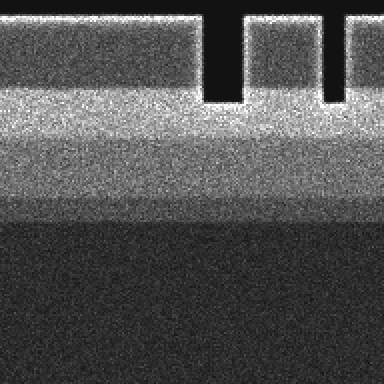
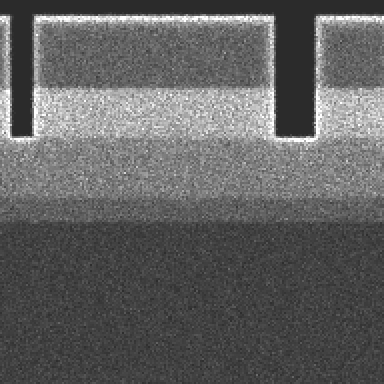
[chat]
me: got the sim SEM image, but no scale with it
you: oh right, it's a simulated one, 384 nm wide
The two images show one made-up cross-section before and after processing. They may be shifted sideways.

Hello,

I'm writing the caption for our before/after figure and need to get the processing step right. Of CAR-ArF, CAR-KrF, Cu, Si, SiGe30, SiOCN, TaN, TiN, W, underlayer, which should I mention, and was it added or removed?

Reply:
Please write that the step removed W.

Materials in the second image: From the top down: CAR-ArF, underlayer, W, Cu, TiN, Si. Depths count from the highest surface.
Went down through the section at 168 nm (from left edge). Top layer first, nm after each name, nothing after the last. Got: CAR-ArF 40, underlayer 32, W 50, Cu 60, TiN 24, Si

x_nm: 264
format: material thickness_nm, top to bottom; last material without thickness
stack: CAR-ArF 40, underlayer 32, W 50, Cu 60, TiN 24, Si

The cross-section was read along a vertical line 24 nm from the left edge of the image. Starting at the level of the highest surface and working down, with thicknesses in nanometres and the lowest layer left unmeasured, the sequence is empty 122, Cu 60, TiN 24, Si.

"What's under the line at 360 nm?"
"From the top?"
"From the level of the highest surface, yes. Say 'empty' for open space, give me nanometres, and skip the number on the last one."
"CAR-ArF 40, underlayer 32, W 50, Cu 60, TiN 24, Si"